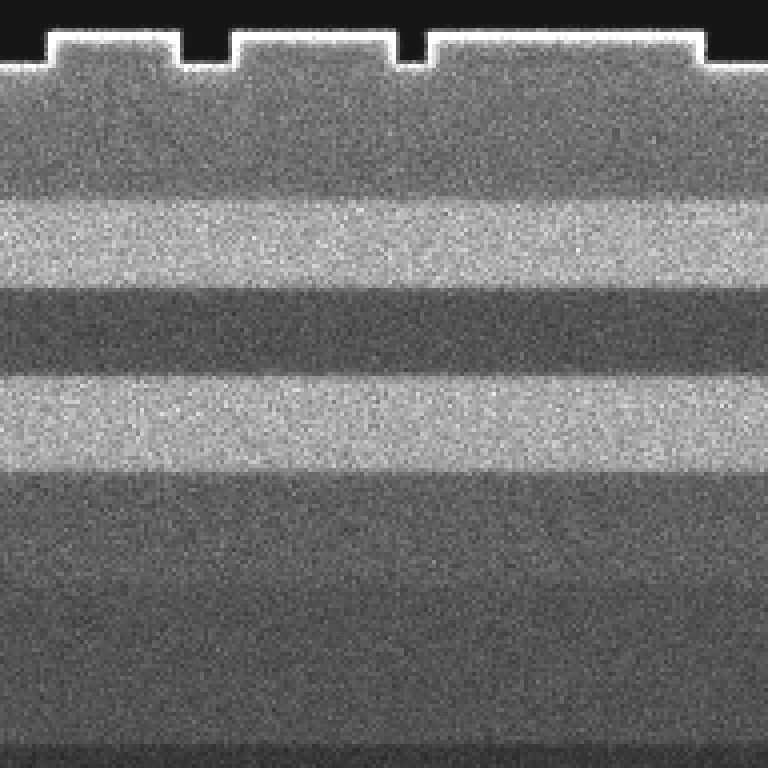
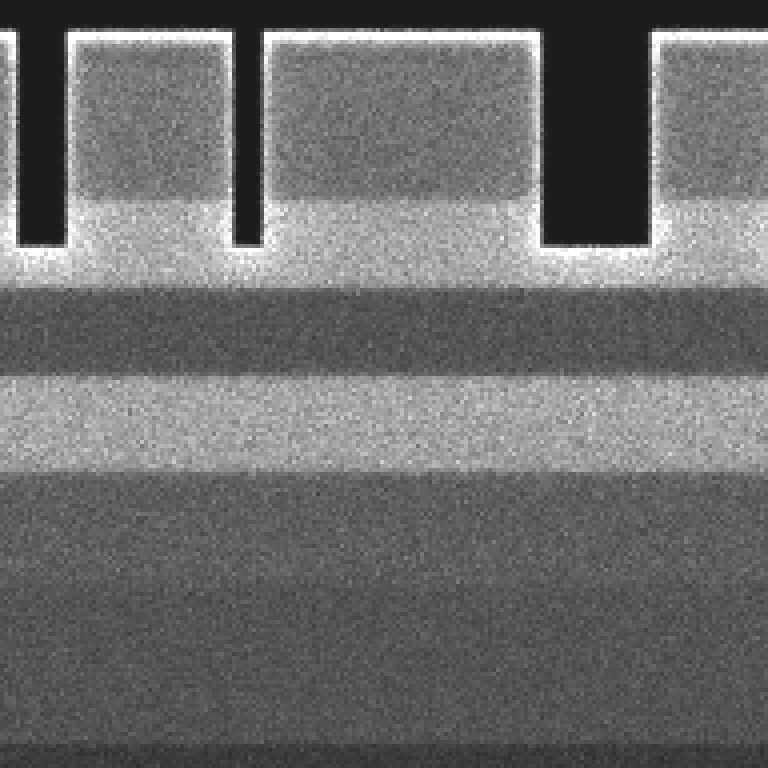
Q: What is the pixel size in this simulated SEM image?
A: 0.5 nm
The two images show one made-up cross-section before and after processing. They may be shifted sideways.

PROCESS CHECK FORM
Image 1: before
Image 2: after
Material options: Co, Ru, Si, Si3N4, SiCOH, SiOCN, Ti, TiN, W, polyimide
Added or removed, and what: removed, Ru and TiN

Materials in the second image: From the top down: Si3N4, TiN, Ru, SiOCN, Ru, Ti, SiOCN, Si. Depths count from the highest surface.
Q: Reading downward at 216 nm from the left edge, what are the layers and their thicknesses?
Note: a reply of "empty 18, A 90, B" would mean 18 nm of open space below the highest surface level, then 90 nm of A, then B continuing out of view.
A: Si3N4 16, TiN 68, Ru 44, SiOCN 44, Ru 48, Ti 56, SiOCN 80, Si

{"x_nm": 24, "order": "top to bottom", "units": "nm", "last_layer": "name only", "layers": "empty 108, Ru 20, SiOCN 44, Ru 48, Ti 56, SiOCN 80, Si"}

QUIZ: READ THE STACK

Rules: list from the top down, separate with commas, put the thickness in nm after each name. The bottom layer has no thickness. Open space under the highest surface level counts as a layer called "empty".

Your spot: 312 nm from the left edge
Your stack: empty 108, Ru 20, SiOCN 44, Ru 48, Ti 56, SiOCN 80, Si